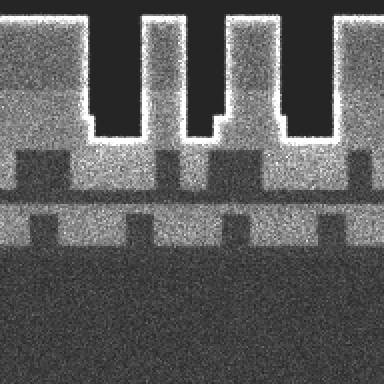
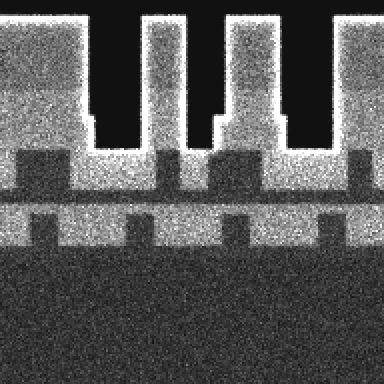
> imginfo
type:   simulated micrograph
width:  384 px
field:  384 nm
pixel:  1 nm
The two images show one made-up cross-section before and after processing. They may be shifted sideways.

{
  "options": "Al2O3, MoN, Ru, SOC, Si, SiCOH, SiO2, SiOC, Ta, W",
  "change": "removed",
  "material": "Al2O3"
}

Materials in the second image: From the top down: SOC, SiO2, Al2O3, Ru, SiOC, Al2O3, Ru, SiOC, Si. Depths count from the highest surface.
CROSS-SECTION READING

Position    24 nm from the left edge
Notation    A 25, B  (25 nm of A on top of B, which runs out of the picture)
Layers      SOC 74, SiO2 48, Al2O3 12, SiOC 54, Al2O3 10, Ru 32, SiOC 12, Si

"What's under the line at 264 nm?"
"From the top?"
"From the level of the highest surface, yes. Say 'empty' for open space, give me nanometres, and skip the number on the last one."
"SOC 74, SiO2 48, Al2O3 12, Ru 40, SiOC 14, Al2O3 10, Ru 32, SiOC 12, Si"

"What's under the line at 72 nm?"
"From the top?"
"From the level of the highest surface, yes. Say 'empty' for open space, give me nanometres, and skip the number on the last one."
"SOC 74, SiO2 48, Al2O3 12, Ru 40, SiOC 14, Al2O3 10, Ru 32, SiOC 12, Si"